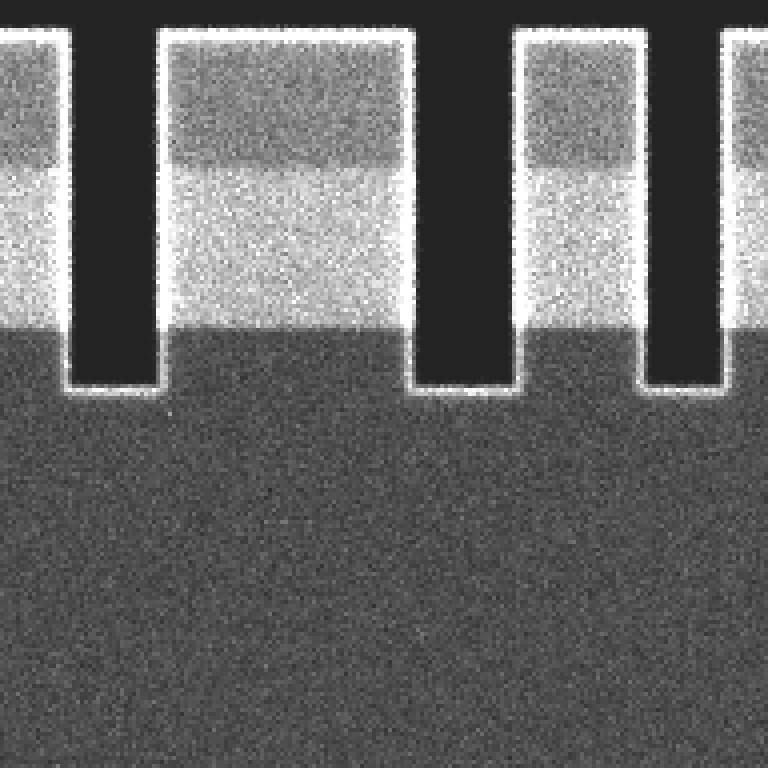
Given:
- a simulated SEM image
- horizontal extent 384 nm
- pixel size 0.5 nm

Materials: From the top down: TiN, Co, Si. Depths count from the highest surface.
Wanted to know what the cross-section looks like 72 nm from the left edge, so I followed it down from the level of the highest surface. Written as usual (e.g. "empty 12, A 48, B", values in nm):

empty 178, Si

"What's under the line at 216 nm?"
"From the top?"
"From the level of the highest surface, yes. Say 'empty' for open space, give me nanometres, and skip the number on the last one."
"empty 178, Si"